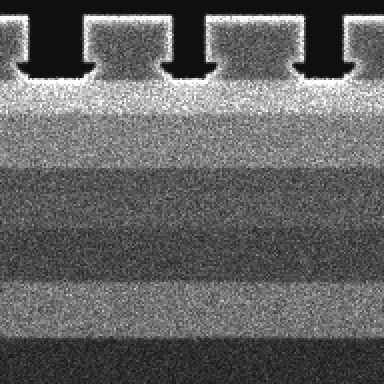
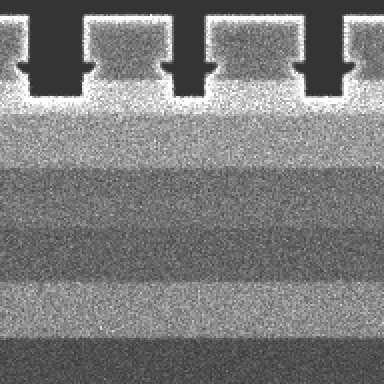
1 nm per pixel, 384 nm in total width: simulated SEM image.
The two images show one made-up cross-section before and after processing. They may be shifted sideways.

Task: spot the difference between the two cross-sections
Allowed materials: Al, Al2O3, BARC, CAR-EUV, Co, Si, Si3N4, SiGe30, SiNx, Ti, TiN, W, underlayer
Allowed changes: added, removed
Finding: removed W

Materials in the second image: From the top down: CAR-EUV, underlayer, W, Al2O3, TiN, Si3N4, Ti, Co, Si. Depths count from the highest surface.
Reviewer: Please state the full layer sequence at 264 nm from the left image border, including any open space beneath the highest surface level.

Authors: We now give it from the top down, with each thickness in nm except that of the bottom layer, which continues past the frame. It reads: CAR-EUV 46, underlayer 18, W 34, Al2O3 54, TiN 24, Si3N4 36, Ti 54, Co 56, Si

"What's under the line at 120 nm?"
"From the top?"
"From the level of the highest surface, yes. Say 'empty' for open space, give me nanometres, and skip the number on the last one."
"CAR-EUV 46, underlayer 18, W 34, Al2O3 54, TiN 24, Si3N4 36, Ti 54, Co 56, Si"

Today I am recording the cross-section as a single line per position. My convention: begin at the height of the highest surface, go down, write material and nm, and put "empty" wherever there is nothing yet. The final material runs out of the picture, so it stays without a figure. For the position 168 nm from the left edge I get CAR-EUV 46, empty 12, underlayer 6, W 34, Al2O3 54, TiN 24, Si3N4 36, Ti 54, Co 56, Si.